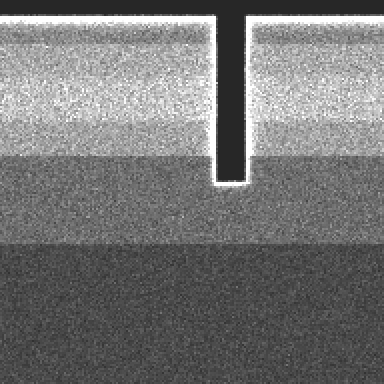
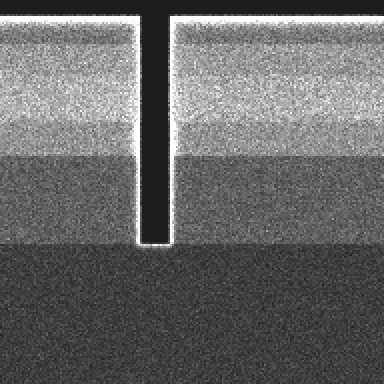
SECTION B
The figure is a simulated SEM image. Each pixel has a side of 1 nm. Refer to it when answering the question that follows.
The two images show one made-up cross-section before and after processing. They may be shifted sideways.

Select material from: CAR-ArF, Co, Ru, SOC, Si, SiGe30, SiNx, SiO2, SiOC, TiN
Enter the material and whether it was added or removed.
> SiNx / removed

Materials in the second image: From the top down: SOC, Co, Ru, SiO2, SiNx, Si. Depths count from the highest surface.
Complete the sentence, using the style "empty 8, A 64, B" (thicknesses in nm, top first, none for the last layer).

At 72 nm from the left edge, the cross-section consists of SOC 28, Co 32, Ru 46, SiO2 34, SiNx 88, Si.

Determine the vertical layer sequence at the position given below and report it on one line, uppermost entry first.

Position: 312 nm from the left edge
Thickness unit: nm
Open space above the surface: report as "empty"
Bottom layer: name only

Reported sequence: SOC 28, Co 32, Ru 46, SiO2 34, SiNx 88, Si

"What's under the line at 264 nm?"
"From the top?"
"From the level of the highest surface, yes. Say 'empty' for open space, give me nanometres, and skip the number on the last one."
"SOC 28, Co 32, Ru 46, SiO2 34, SiNx 88, Si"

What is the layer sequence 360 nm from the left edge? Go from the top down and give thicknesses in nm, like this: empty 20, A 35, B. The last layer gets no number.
SOC 28, Co 32, Ru 46, SiO2 34, SiNx 88, Si